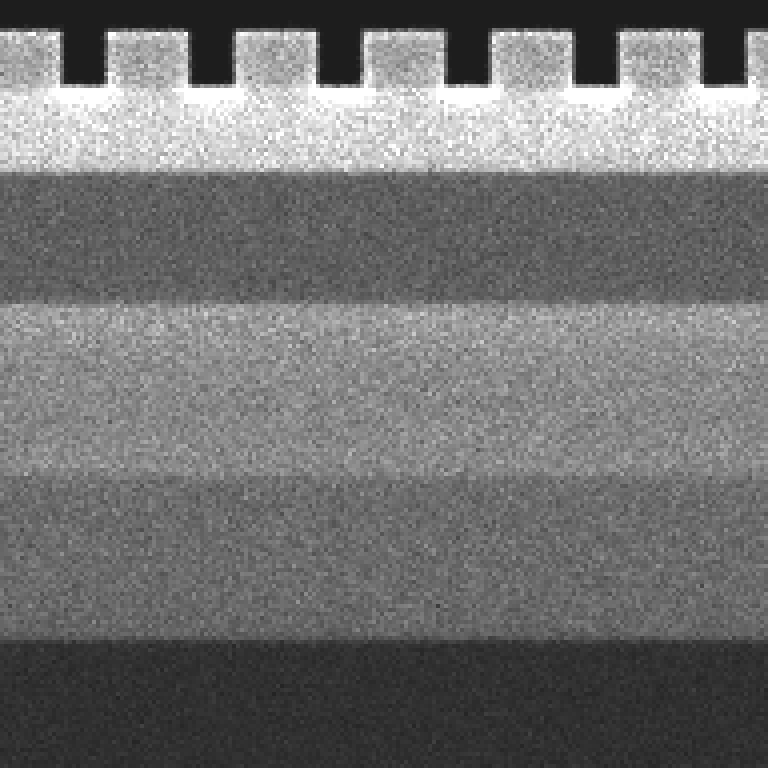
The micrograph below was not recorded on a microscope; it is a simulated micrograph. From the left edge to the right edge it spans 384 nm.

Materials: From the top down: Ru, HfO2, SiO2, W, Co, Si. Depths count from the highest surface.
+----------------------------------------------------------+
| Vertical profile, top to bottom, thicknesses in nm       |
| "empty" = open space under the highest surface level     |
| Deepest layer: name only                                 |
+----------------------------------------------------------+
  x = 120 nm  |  Ru 28, HfO2 42, SiO2 66, W 86, Co 82, Si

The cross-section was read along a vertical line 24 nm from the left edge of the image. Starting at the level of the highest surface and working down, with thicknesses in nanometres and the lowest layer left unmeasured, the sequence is Ru 28, HfO2 42, SiO2 66, W 86, Co 82, Si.